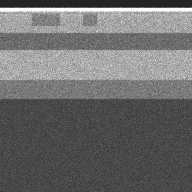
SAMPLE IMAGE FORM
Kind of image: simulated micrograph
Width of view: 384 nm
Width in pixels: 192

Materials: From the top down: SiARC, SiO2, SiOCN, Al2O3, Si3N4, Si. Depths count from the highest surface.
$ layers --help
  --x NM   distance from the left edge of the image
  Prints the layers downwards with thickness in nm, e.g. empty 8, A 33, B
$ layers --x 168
SiARC 36, SiO2 14, SiOCN 34, Al2O3 60, Si3N4 38, Si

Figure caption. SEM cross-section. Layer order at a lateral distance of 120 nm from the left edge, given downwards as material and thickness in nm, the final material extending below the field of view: SiARC 12, SiO2 38, SiOCN 34, Al2O3 60, Si3N4 38, Si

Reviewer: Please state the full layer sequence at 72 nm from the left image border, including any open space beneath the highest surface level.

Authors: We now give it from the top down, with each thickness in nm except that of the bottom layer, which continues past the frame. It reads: SiARC 36, SiO2 14, SiOCN 34, Al2O3 60, Si3N4 38, Si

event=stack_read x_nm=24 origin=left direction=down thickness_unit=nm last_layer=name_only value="SiARC 12, SiO2 38, SiOCN 34, Al2O3 60, Si3N4 38, Si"